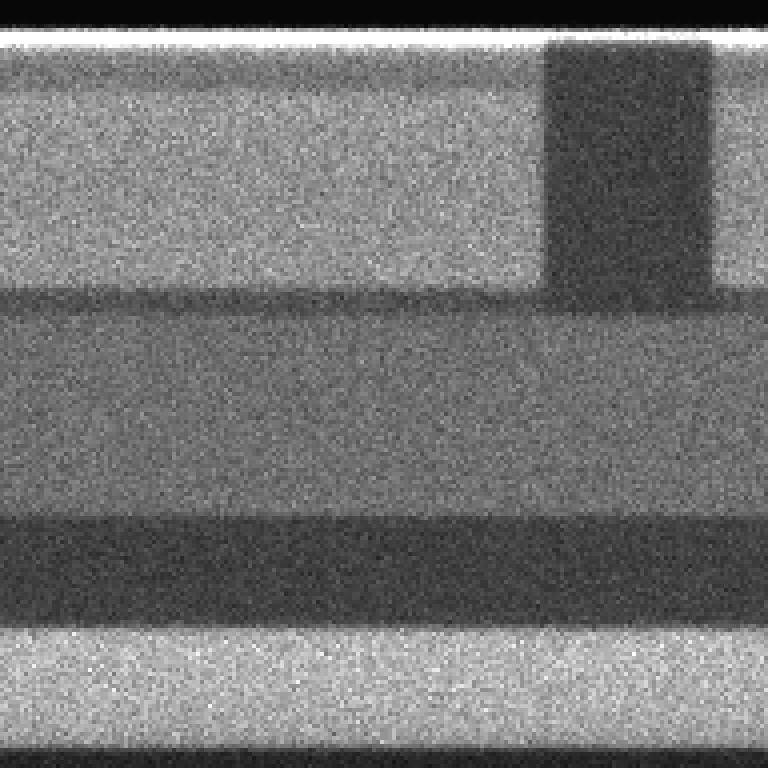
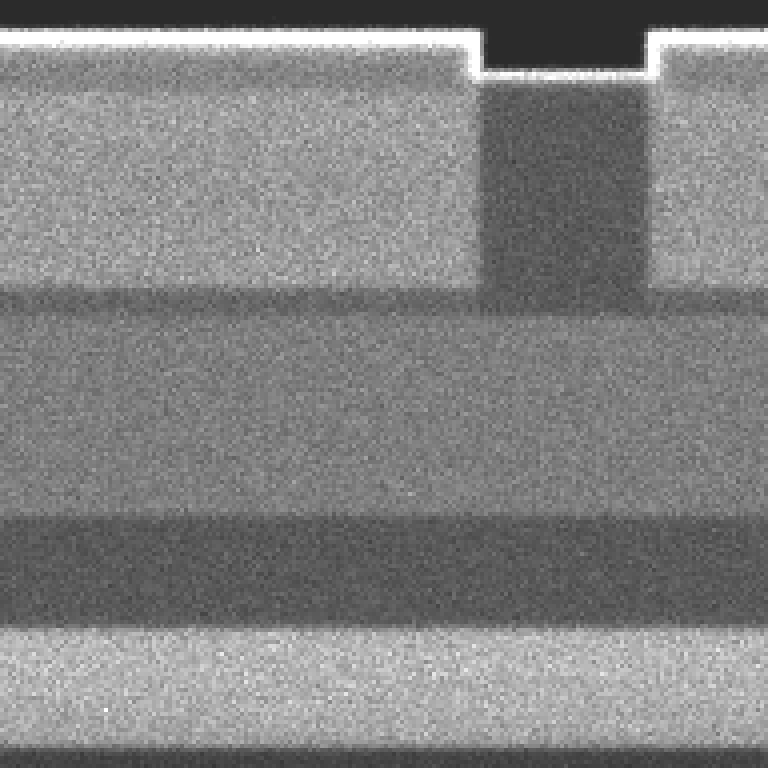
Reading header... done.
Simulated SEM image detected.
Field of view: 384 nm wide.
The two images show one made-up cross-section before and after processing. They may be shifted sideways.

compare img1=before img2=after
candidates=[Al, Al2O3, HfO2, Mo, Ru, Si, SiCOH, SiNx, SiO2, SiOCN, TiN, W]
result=removed:SiNx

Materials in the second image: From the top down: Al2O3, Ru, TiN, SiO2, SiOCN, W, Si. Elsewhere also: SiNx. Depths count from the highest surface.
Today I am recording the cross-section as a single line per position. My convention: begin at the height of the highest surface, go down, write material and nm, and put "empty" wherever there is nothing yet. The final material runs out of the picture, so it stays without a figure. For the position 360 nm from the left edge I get Al2O3 30, Ru 98, TiN 14, SiO2 100, SiOCN 56, W 60, Si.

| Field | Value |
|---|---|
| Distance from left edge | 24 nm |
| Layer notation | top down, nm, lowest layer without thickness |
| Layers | Al2O3 30, Ru 98, TiN 14, SiO2 100, SiOCN 56, W 60, Si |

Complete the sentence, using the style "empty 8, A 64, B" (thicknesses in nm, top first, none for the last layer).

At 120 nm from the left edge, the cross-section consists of Al2O3 30, Ru 98, TiN 14, SiO2 100, SiOCN 56, W 60, Si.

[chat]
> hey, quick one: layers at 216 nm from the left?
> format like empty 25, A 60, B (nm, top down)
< Al2O3 30, Ru 98, TiN 14, SiO2 100, SiOCN 56, W 60, Si